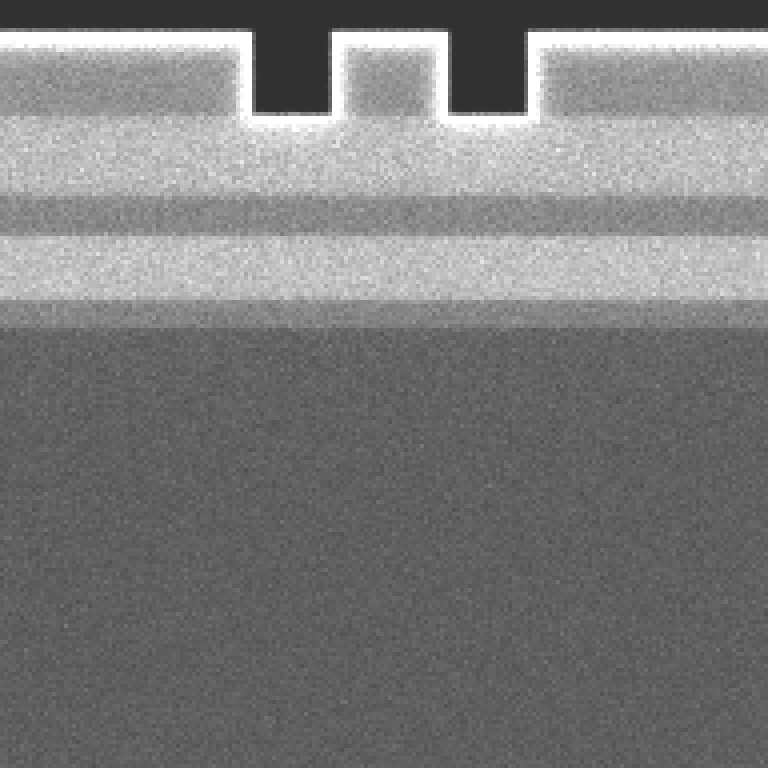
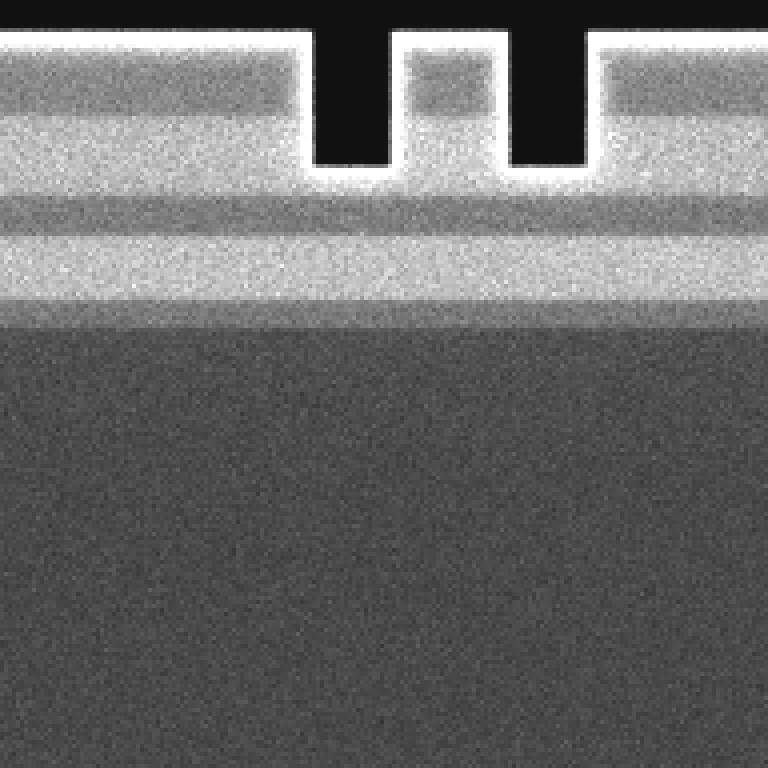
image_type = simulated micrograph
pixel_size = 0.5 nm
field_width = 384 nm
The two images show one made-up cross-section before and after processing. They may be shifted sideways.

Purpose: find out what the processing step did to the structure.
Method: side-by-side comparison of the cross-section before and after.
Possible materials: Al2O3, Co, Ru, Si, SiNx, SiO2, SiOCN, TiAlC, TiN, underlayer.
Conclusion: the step removed TiN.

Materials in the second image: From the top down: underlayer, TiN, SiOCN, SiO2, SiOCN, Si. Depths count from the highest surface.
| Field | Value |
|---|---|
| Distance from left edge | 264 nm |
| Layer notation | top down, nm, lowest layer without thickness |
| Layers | empty 68, TiN 14, SiOCN 20, SiO2 32, SiOCN 14, Si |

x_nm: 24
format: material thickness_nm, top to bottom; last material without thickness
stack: underlayer 42, TiN 40, SiOCN 20, SiO2 32, SiOCN 14, Si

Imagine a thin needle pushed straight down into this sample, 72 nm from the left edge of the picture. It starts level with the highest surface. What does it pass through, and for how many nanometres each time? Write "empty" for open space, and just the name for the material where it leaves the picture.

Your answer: underlayer 42, TiN 40, SiOCN 20, SiO2 32, SiOCN 14, Si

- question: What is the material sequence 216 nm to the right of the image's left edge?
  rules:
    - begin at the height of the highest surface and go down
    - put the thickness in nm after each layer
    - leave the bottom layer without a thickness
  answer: underlayer 42, TiN 40, SiOCN 20, SiO2 32, SiOCN 14, Si